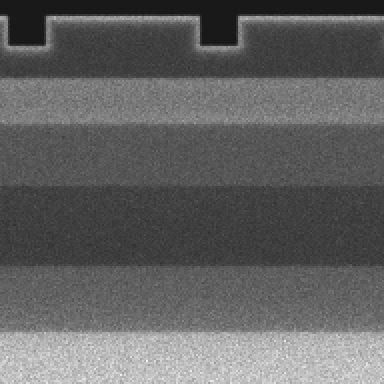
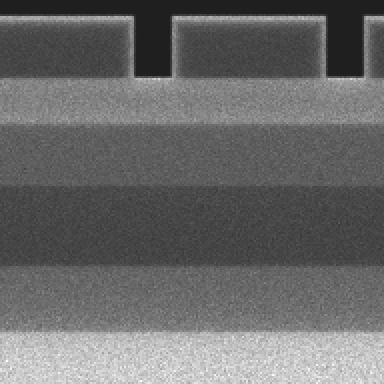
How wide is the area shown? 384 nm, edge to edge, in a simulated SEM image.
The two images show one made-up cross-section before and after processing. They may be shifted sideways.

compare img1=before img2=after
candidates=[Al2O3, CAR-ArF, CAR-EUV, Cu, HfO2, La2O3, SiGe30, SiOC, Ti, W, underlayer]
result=removed:underlayer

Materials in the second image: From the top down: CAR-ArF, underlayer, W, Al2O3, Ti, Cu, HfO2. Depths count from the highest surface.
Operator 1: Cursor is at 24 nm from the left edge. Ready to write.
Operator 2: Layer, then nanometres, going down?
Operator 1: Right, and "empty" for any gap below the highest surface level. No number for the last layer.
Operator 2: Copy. CAR-ArF 30, underlayer 32, W 46, Al2O3 62, Ti 80, Cu 66, HfO2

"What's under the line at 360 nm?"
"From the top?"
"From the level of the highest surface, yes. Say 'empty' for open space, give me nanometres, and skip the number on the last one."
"empty 62, W 46, Al2O3 62, Ti 80, Cu 66, HfO2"